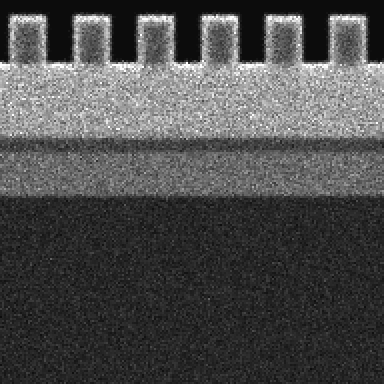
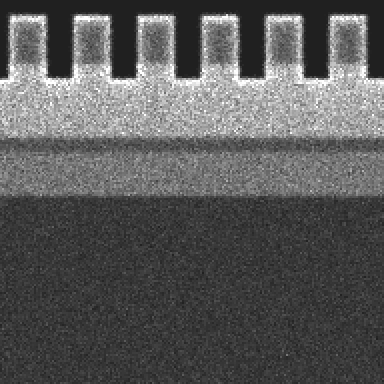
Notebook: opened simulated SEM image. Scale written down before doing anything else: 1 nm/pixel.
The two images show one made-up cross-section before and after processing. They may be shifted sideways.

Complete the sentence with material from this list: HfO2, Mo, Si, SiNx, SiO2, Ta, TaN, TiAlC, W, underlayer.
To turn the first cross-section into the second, W must be removed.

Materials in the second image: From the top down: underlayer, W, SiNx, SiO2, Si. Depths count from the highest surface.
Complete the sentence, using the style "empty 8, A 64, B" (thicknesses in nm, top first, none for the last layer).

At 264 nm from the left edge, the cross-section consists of empty 64, W 58, SiNx 14, SiO2 44, Si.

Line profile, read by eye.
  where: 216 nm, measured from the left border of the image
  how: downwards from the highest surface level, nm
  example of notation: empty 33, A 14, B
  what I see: underlayer 48, W 74, SiNx 14, SiO2 44, Si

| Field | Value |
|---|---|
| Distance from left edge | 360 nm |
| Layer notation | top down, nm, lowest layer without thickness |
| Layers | underlayer 48, W 74, SiNx 14, SiO2 44, Si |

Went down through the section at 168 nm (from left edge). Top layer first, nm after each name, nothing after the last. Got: underlayer 48, W 74, SiNx 14, SiO2 44, Si